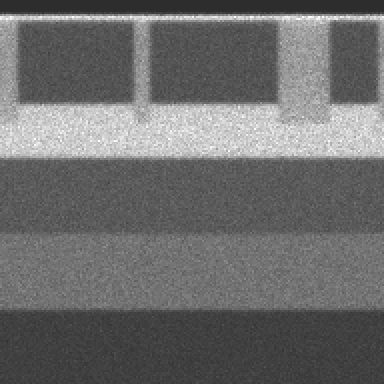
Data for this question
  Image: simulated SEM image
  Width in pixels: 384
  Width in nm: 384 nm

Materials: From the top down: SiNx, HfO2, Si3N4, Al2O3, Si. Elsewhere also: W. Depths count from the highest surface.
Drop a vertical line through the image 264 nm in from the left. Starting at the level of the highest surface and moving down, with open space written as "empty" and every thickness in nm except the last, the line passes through SiNx 88, HfO2 54, Si3N4 76, Al2O3 76, Si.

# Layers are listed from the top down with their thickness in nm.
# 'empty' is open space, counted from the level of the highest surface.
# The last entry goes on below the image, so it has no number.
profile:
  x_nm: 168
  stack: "SiNx 88, HfO2 54, Si3N4 76, Al2O3 76, Si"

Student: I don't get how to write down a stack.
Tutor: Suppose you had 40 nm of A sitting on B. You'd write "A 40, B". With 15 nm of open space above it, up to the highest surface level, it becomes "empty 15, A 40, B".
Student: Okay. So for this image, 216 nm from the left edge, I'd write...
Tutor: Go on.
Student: SiNx 88, HfO2 54, Si3N4 76, Al2O3 76, Si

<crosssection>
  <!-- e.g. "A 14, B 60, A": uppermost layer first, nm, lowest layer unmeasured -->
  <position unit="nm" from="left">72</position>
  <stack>SiNx 88, HfO2 54, Si3N4 76, Al2O3 76, Si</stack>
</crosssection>